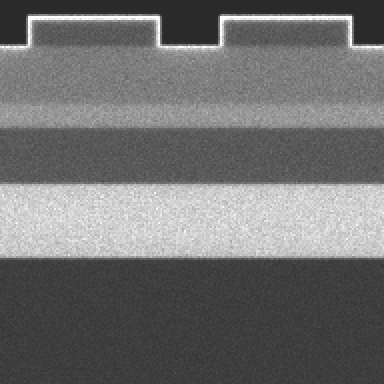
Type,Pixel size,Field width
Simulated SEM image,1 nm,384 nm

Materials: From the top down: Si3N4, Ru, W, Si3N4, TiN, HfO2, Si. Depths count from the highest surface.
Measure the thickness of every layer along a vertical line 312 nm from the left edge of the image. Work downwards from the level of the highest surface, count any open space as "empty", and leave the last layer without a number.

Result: Si3N4 30, Ru 58, W 24, Si3N4 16, TiN 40, HfO2 74, Si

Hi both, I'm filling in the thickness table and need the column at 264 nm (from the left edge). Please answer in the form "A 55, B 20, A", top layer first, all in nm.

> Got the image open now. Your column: Si3N4 30, Ru 58, W 24, Si3N4 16, TiN 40, HfO2 74, Si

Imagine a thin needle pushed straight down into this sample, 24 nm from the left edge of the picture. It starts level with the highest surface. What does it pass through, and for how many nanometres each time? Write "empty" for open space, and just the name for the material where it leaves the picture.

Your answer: empty 30, Ru 58, W 24, Si3N4 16, TiN 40, HfO2 74, Si